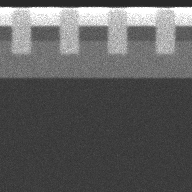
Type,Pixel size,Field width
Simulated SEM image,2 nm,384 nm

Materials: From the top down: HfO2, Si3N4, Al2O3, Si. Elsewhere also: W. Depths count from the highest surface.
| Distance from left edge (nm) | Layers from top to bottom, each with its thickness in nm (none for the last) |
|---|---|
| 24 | W 92, Al2O3 48, Si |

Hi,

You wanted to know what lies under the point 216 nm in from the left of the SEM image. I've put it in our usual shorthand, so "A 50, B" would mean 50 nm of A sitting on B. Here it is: W 92, Al2O3 48, Si